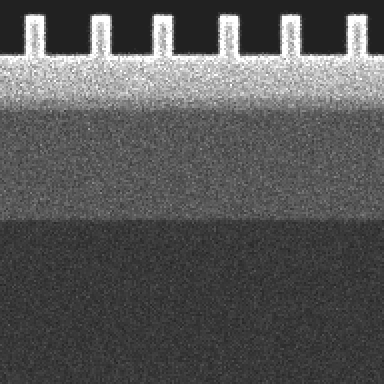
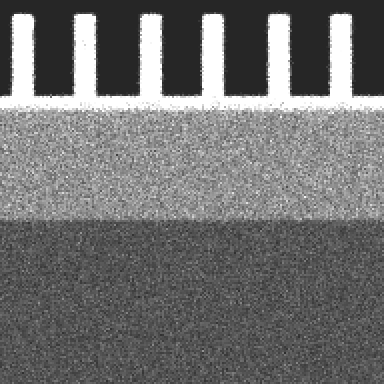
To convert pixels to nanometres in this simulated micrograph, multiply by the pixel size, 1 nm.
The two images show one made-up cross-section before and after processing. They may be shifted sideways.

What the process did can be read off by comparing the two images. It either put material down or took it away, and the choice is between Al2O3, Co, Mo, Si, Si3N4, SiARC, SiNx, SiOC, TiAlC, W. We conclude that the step removed W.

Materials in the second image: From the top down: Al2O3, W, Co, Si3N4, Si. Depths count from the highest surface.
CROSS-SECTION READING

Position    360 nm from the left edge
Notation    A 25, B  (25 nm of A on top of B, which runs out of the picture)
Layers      empty 82, Co 12, Si3N4 110, Si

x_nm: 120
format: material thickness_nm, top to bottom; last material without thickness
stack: empty 82, Co 12, Si3N4 110, Si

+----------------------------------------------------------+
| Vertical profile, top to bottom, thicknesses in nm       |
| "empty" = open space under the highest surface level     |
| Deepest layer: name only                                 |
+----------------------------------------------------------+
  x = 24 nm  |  Al2O3 40, W 42, Co 12, Si3N4 110, Si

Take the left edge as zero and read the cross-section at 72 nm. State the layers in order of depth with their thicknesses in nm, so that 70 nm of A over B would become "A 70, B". empty 82, Co 12, Si3N4 110, Si